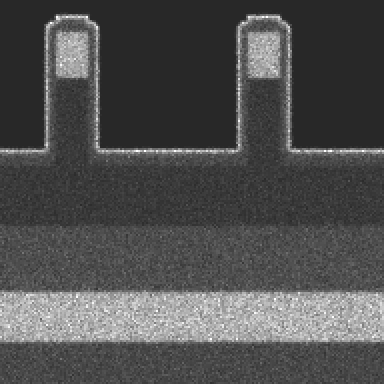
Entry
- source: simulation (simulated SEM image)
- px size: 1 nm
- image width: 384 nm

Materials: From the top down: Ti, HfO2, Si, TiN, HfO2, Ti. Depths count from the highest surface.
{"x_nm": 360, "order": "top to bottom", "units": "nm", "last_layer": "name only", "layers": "empty 134, Ti 16, Si 60, TiN 66, HfO2 50, Ti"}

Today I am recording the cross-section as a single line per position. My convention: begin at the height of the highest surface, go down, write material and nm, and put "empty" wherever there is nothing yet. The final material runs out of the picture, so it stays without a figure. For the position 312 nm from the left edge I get empty 134, Ti 16, Si 60, TiN 66, HfO2 50, Ti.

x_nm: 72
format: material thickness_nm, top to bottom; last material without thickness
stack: Ti 16, HfO2 46, Si 148, TiN 66, HfO2 50, Ti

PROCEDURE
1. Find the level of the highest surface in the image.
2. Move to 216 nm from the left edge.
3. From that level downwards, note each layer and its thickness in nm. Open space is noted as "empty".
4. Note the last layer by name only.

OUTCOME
empty 134, Ti 16, Si 60, TiN 66, HfO2 50, Ti